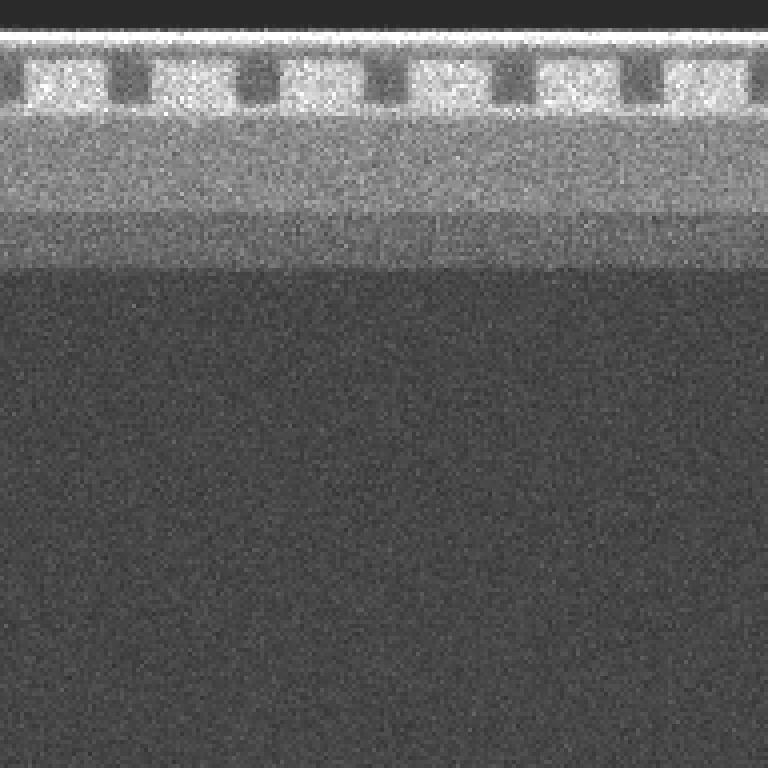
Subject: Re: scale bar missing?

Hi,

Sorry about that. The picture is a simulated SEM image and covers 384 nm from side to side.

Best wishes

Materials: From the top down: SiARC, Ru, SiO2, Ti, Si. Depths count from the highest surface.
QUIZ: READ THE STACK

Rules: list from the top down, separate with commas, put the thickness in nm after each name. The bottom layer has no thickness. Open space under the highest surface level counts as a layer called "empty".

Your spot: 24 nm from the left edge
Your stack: SiARC 14, Ru 28, SiO2 48, Ti 28, Si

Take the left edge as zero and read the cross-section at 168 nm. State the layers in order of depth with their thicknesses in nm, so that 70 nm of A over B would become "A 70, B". SiARC 14, Ru 28, SiO2 48, Ti 28, Si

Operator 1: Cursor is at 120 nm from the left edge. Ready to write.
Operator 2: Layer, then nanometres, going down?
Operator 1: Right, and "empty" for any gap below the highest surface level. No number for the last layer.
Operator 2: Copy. SiARC 36, Ru 6, SiO2 48, Ti 28, Si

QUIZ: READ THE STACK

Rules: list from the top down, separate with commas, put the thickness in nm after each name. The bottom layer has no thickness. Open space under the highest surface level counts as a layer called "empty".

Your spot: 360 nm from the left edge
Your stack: SiARC 14, Ru 28, SiO2 48, Ti 28, Si